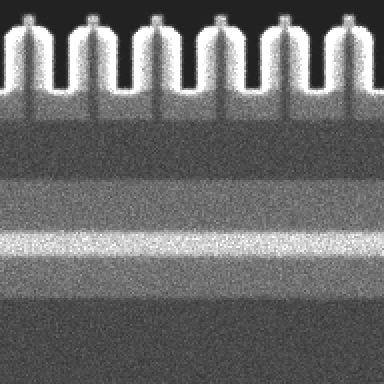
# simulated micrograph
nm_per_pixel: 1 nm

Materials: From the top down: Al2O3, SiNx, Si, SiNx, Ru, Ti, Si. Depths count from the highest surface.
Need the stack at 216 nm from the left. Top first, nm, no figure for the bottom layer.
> Si 164, SiNx 52, Ru 24, Ti 42, Si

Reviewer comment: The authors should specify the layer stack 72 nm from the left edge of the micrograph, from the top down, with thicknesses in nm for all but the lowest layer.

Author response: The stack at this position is empty 18, Al2O3 56, SiNx 30, Si 60, SiNx 52, Ru 24, Ti 42, Si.